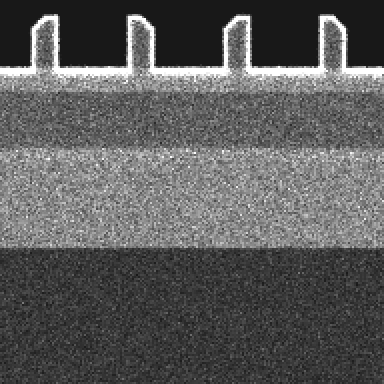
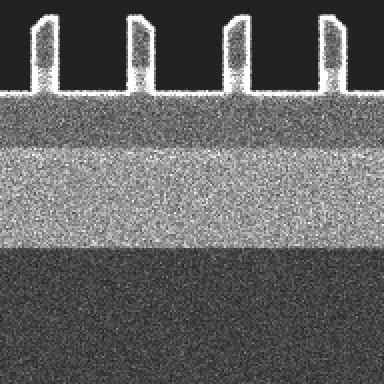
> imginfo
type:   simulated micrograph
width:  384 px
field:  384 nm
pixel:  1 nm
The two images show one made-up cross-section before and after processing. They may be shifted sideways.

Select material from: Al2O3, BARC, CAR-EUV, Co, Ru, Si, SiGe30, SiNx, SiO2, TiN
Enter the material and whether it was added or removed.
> Al2O3 / removed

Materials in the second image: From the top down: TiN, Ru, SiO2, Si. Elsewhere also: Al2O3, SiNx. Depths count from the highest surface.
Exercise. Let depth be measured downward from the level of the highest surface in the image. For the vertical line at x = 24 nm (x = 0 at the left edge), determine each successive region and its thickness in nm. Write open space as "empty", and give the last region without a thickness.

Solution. empty 76, TiN 56, Ru 14, SiO2 86, Si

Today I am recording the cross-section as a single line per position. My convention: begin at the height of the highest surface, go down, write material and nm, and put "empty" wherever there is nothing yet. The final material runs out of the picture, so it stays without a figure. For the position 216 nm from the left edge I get empty 76, TiN 56, Ru 14, SiO2 86, Si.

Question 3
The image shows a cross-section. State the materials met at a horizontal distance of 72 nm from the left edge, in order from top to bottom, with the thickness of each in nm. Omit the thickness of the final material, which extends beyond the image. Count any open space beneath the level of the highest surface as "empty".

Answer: empty 76, TiN 56, Ru 14, SiO2 86, Si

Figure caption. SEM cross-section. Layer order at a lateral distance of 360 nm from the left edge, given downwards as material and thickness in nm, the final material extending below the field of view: empty 76, TiN 56, Ru 14, SiO2 86, Si